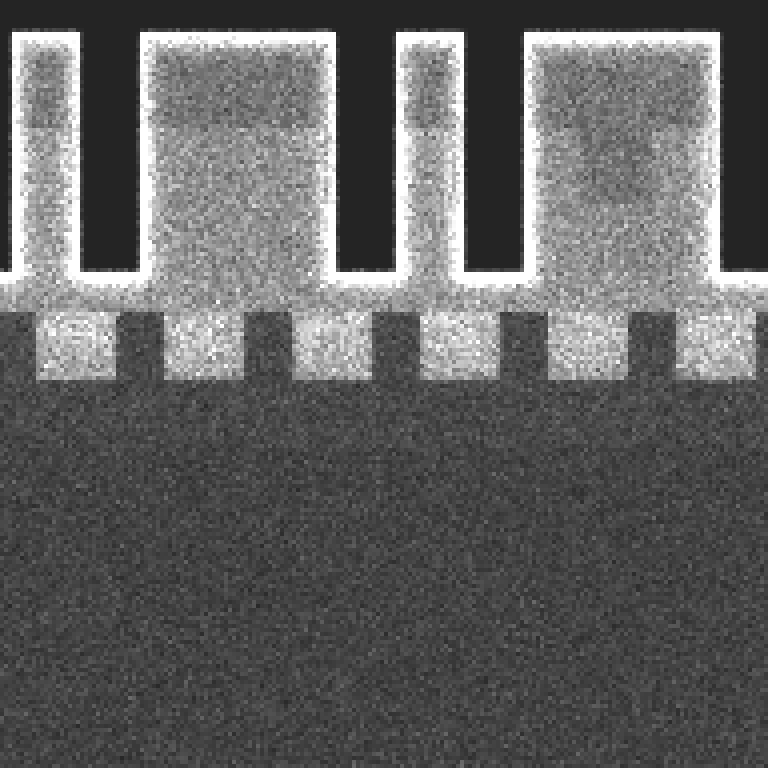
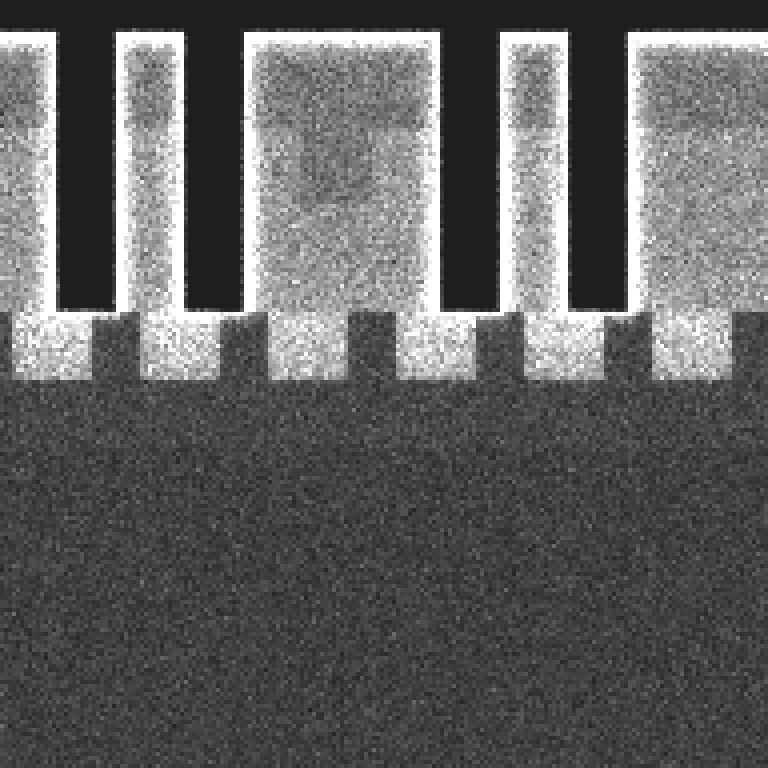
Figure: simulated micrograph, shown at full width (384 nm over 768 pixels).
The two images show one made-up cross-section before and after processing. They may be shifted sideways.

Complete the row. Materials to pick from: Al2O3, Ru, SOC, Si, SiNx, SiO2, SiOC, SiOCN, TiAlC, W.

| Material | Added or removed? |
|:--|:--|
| Al2O3 | removed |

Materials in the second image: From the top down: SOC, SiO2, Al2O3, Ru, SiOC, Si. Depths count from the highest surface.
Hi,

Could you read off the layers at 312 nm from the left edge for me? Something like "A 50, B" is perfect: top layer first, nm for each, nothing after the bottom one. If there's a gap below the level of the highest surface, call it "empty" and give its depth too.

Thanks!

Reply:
empty 140, SiOC 68, Si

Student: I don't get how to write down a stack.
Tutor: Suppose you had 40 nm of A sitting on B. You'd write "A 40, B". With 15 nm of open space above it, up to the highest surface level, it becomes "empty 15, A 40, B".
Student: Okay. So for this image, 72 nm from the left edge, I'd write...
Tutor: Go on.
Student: SOC 48, SiO2 72, Al2O3 20, Ru 34, SiOC 34, Si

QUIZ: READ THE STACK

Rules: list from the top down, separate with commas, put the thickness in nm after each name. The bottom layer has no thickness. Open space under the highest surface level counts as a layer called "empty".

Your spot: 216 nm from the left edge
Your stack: SOC 86, SiO2 34, Al2O3 20, Ru 34, SiOC 34, Si